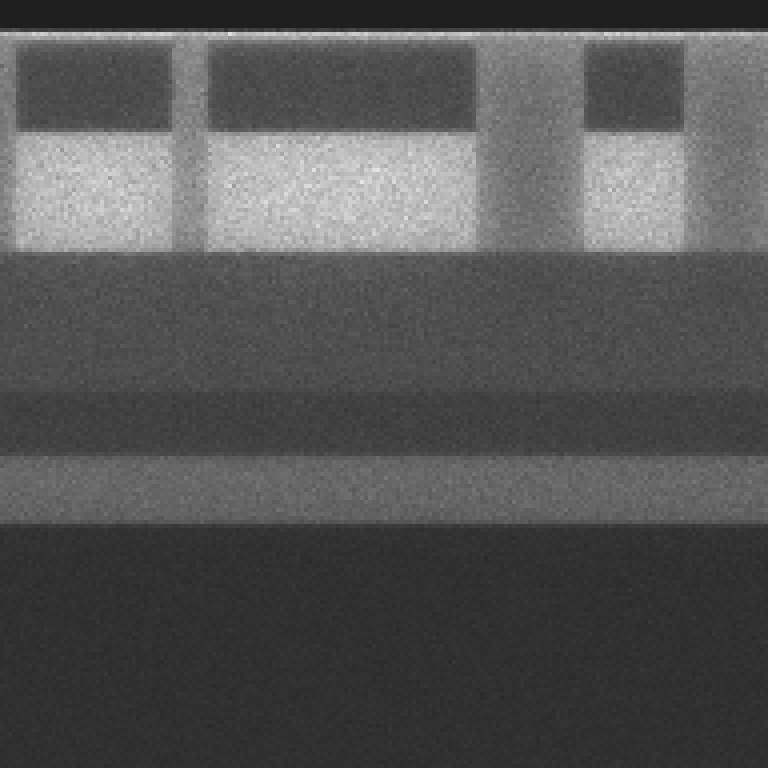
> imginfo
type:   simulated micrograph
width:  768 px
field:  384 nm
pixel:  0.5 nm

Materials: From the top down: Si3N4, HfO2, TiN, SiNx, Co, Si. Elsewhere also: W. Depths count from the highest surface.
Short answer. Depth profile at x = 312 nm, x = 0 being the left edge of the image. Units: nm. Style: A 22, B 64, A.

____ Si3N4 50, HfO2 60, TiN 70, SiNx 32, Co 34, Si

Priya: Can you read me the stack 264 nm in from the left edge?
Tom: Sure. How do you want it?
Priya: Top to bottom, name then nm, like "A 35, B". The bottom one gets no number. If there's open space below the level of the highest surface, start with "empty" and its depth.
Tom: W 110, TiN 70, SiNx 32, Co 34, Si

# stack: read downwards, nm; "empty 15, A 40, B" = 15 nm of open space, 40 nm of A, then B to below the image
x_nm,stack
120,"Si3N4 50, HfO2 60, TiN 70, SiNx 32, Co 34, Si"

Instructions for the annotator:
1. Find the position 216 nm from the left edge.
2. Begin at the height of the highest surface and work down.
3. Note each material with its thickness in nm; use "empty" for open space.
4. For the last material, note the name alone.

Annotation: Si3N4 50, HfO2 60, TiN 70, SiNx 32, Co 34, Si